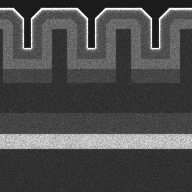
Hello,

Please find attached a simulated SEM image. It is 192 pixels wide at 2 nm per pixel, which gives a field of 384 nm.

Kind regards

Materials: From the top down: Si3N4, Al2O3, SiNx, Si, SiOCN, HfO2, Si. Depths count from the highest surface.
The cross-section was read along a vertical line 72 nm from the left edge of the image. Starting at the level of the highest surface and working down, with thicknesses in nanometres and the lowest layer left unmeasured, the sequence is empty 10, Si3N4 92, Al2O3 20, SiNx 28, Si 60, SiOCN 42, HfO2 30, Si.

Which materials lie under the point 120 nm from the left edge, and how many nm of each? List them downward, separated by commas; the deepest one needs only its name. Si3N4 22, Al2O3 20, Si 168, SiOCN 42, HfO2 30, Si